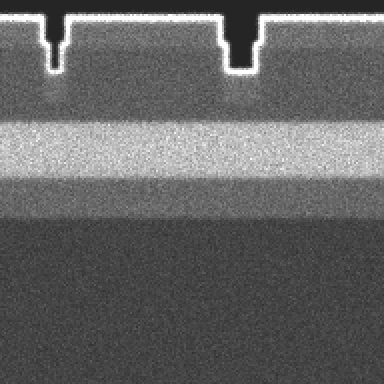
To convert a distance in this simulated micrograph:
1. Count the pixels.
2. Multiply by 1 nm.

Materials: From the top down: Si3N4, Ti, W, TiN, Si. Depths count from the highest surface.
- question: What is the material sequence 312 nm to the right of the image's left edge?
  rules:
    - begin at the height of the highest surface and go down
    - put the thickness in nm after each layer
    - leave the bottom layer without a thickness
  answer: Si3N4 32, Ti 74, W 56, TiN 40, Si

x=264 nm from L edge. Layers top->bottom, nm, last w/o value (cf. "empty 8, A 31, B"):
Si3N4 32, Ti 74, W 56, TiN 40, Si